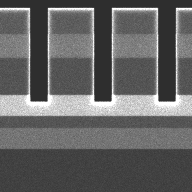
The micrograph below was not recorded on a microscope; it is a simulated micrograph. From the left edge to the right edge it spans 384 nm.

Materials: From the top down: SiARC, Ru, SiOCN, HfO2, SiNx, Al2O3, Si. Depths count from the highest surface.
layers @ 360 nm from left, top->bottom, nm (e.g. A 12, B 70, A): SiARC 52, Ru 48, SiOCN 74, HfO2 42, SiNx 24, Al2O3 42, Si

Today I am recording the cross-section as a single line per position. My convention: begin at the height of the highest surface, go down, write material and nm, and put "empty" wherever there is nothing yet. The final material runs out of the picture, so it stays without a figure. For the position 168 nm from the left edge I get SiARC 52, Ru 48, SiOCN 74, HfO2 42, SiNx 24, Al2O3 42, Si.